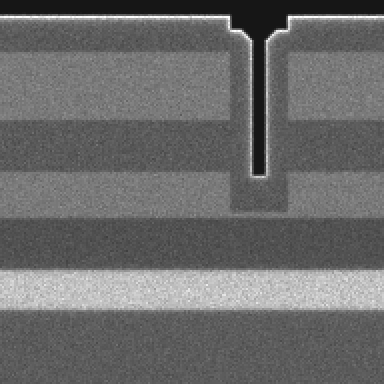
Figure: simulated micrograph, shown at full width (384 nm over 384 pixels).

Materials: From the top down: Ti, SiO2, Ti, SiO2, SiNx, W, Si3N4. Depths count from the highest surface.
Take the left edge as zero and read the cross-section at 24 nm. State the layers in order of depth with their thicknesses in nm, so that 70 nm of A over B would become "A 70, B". Ti 36, SiO2 68, Ti 52, SiO2 46, SiNx 52, W 40, Si3N4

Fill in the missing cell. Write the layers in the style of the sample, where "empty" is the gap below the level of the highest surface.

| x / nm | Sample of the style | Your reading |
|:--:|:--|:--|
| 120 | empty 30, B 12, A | Ti 36, SiO2 68, Ti 52, SiO2 46, SiNx 52, W 40, Si3N4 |